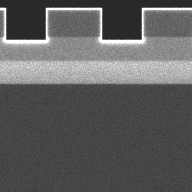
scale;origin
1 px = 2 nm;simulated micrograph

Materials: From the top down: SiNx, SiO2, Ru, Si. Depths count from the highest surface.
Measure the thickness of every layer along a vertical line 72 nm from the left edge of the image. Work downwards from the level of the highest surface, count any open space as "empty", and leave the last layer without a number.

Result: empty 64, SiO2 42, Ru 46, Si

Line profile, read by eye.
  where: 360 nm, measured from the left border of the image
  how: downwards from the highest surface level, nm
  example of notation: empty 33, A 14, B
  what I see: SiNx 58, SiO2 48, Ru 46, Si